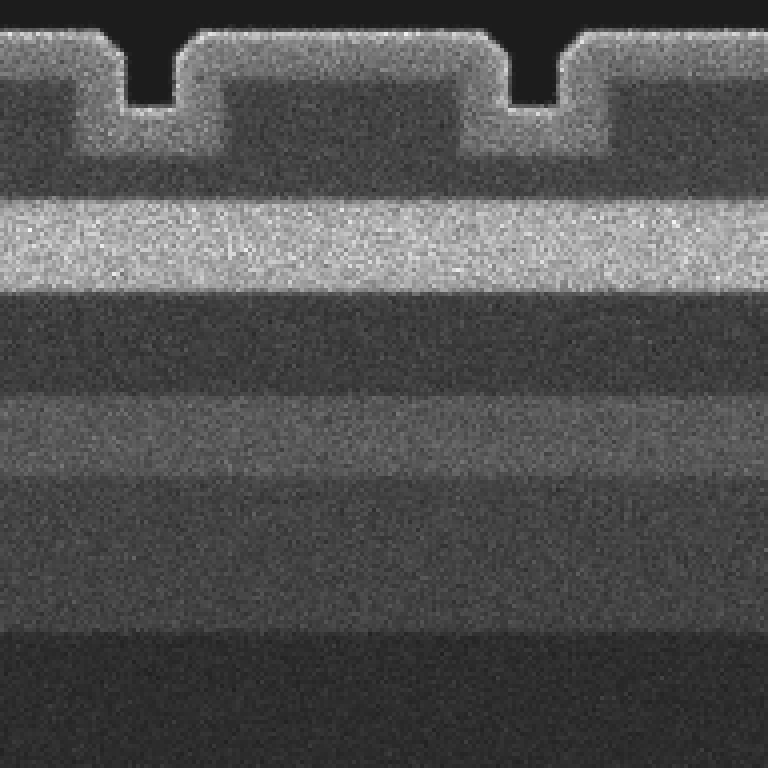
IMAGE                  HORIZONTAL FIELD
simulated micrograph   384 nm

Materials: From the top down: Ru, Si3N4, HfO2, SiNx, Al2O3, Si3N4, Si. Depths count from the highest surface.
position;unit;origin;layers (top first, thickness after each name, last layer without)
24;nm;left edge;Ru 24, Si3N4 60, HfO2 46, SiNx 52, Al2O3 40, Si3N4 78, Si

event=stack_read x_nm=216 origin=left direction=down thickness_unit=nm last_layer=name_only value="Ru 24, Si3N4 60, HfO2 46, SiNx 52, Al2O3 40, Si3N4 78, Si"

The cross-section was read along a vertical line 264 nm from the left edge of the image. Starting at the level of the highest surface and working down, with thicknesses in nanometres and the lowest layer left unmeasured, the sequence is empty 38, Ru 24, Si3N4 22, HfO2 46, SiNx 52, Al2O3 40, Si3N4 78, Si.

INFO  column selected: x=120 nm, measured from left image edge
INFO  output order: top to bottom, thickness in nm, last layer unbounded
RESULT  Ru 24, Si3N4 60, HfO2 46, SiNx 52, Al2O3 40, Si3N4 78, Si